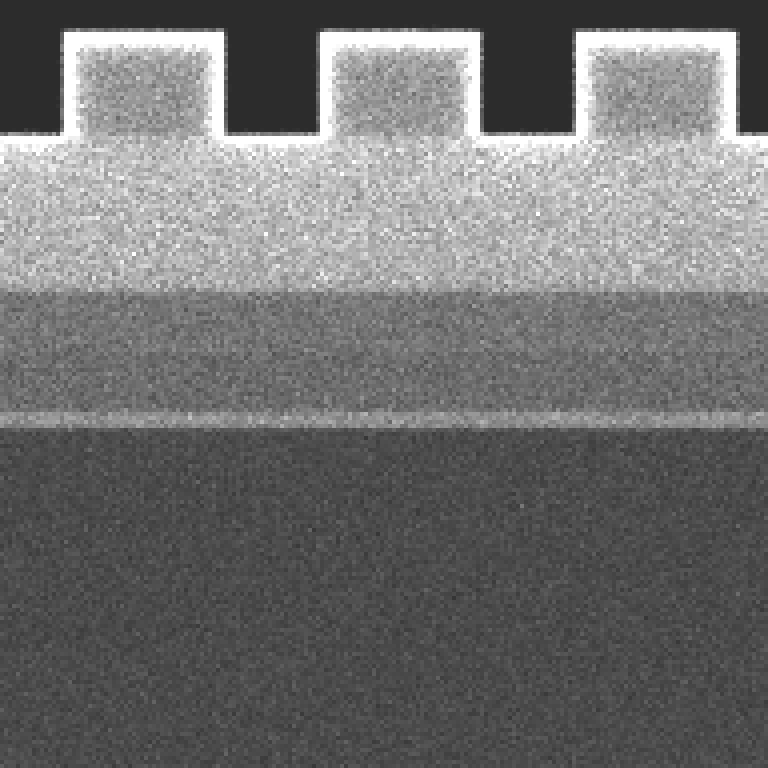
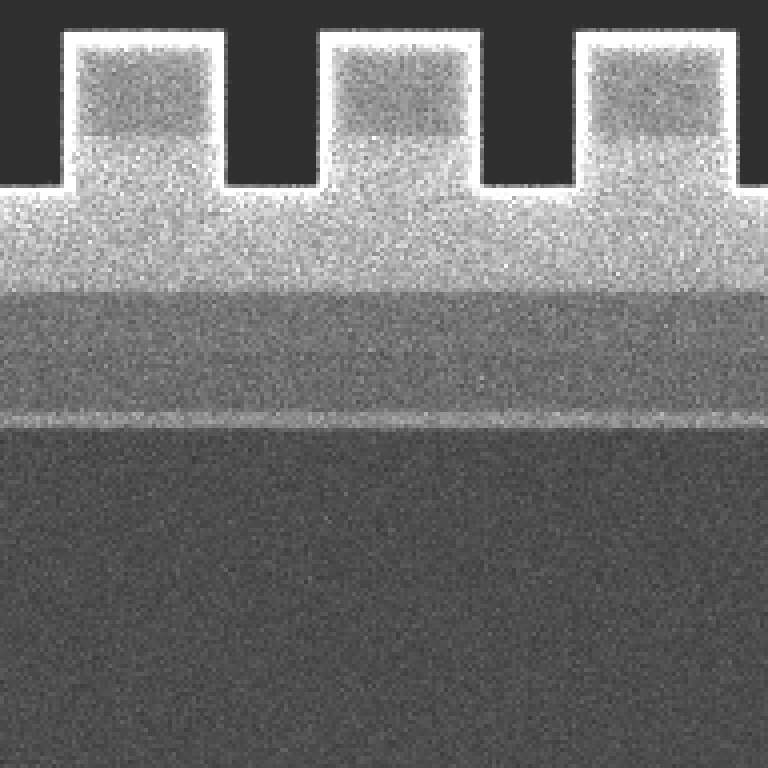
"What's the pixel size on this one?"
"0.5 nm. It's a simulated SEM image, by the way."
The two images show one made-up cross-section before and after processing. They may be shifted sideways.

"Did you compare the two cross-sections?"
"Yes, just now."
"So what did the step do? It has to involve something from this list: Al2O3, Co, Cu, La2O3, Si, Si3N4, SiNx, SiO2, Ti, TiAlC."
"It removed Co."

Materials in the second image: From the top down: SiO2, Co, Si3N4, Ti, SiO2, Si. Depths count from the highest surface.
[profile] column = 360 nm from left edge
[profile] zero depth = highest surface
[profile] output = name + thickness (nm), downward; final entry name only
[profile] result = SiO2 52, Co 78, Si3N4 30, Ti 30, SiO2 8, Si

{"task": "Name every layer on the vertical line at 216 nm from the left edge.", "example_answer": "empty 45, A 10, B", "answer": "SiO2 52, Co 78, Si3N4 30, Ti 30, SiO2 8, Si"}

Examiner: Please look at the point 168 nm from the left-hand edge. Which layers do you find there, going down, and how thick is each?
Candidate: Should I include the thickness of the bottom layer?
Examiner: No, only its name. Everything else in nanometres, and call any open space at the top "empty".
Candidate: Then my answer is SiO2 52, Co 78, Si3N4 30, Ti 30, SiO2 8, Si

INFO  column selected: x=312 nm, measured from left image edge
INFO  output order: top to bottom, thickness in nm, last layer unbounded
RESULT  SiO2 52, Co 78, Si3N4 30, Ti 30, SiO2 8, Si